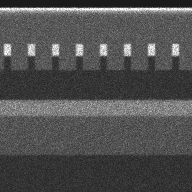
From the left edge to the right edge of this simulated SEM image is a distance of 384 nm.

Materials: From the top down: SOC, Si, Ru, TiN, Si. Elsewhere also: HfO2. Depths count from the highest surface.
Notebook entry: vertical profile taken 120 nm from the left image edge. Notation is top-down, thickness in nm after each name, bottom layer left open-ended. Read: SOC 124, Si 60, Ru 32, TiN 78, Si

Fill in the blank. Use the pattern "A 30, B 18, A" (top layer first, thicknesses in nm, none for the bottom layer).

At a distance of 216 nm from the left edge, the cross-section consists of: SOC 124, Si 60, Ru 32, TiN 78, Si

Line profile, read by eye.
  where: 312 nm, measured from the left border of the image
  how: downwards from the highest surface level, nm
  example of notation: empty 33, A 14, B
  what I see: SOC 124, Si 60, Ru 32, TiN 78, Si